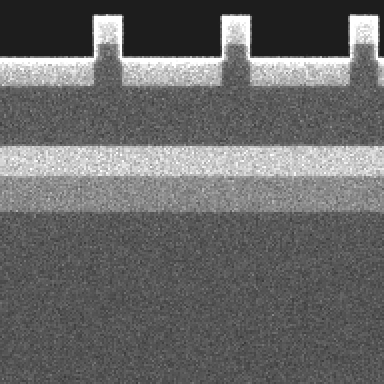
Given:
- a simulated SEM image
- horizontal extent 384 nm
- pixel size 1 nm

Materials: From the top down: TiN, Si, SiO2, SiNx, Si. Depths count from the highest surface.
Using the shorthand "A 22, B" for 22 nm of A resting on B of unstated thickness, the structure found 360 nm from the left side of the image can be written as TiN 28, Si 102, SiO2 30, SiNx 36, Si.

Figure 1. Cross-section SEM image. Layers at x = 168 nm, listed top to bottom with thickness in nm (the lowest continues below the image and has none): empty 42, TiN 28, Si 60, SiO2 30, SiNx 36, Si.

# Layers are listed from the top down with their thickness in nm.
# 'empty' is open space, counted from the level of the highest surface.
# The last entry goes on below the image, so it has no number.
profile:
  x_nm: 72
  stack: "empty 42, TiN 28, Si 60, SiO2 30, SiNx 36, Si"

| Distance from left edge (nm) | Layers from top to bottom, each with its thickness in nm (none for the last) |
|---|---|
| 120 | TiN 28, Si 102, SiO2 30, SiNx 36, Si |